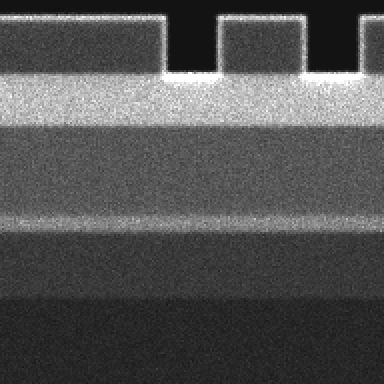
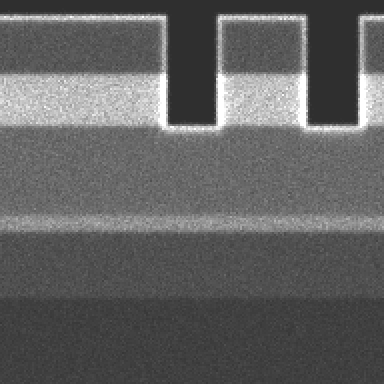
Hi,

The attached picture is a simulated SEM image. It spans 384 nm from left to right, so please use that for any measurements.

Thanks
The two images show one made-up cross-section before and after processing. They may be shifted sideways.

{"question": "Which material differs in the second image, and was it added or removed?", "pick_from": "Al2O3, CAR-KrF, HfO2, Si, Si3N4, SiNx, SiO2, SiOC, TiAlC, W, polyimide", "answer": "HfO2, removed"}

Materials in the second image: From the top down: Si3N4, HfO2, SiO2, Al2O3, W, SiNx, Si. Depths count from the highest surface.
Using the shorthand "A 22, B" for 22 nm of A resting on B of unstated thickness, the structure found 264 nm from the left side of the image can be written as Si3N4 58, HfO2 52, SiO2 80, Al2O3 10, W 16, SiNx 66, Si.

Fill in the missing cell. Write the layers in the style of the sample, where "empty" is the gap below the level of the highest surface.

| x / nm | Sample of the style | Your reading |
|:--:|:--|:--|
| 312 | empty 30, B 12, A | empty 110, SiO2 80, Al2O3 10, W 16, SiNx 66, Si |